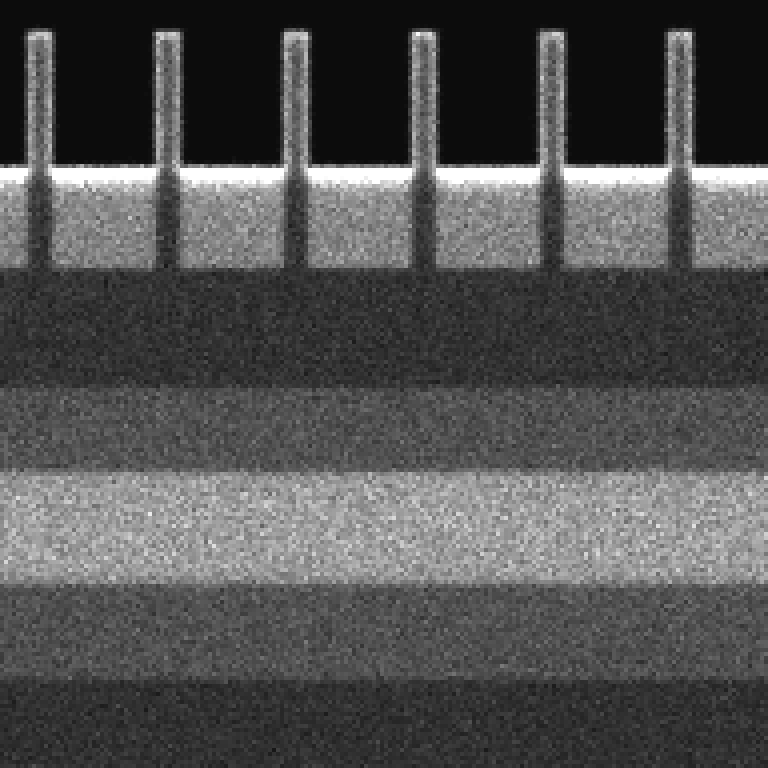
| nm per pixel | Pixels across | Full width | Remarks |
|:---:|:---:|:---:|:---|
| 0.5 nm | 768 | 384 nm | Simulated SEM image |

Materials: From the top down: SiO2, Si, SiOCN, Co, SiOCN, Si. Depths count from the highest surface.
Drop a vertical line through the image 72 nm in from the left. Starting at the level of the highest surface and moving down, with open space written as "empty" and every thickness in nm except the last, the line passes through empty 68, SiO2 50, Si 60, SiOCN 42, Co 56, SiOCN 48, Si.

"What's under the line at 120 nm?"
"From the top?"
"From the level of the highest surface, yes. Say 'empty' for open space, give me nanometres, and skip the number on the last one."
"empty 68, SiO2 50, Si 60, SiOCN 42, Co 56, SiOCN 48, Si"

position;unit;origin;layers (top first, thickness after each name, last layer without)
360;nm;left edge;empty 68, SiO2 50, Si 60, SiOCN 42, Co 56, SiOCN 48, Si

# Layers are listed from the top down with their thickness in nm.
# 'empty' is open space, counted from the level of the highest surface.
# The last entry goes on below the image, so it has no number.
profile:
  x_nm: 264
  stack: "empty 68, SiO2 50, Si 60, SiOCN 42, Co 56, SiOCN 48, Si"